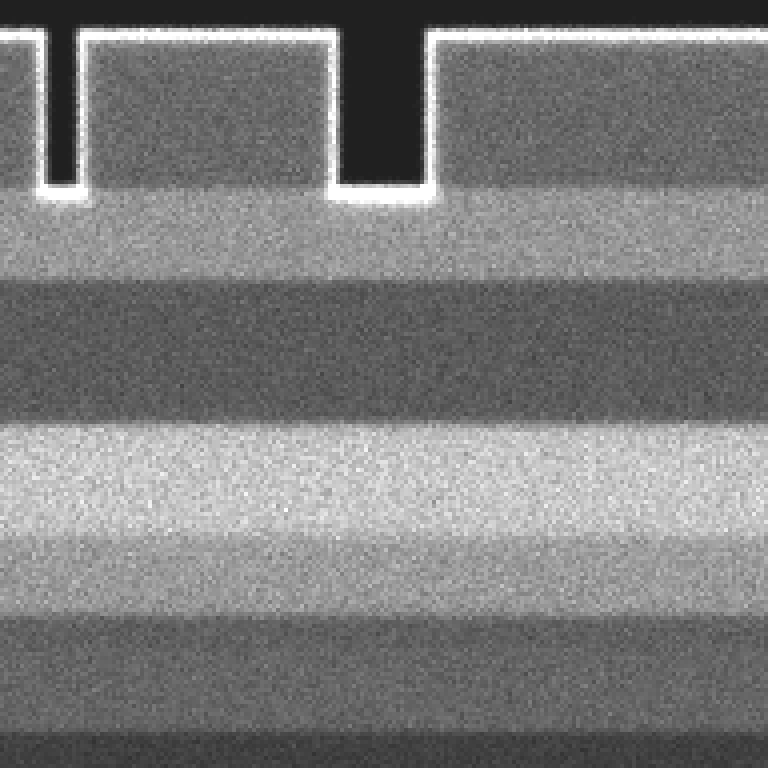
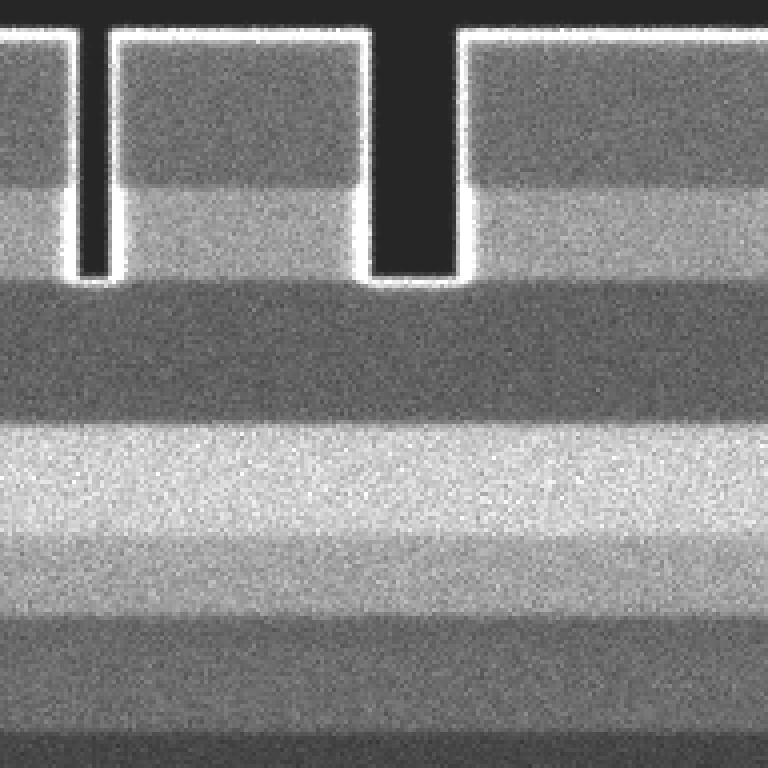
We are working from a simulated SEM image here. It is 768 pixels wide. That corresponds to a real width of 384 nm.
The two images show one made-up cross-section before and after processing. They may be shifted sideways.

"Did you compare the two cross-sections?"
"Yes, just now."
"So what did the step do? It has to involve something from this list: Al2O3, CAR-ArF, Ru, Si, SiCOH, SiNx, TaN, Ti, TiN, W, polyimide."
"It removed Al2O3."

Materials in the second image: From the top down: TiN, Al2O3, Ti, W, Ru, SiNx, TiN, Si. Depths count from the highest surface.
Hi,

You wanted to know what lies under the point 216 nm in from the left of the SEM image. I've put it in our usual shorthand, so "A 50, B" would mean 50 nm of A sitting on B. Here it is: empty 124, Ti 72, W 56, Ru 40, SiNx 16, TiN 42, Si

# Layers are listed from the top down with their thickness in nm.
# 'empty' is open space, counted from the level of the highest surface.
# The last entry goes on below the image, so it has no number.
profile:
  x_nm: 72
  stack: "TiN 78, Al2O3 46, Ti 72, W 56, Ru 40, SiNx 16, TiN 42, Si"